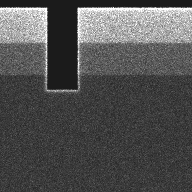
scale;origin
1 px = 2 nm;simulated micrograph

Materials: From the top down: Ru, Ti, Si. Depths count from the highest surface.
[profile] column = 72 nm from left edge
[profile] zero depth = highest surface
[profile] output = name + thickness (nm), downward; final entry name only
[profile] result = Ru 70, Ti 64, Si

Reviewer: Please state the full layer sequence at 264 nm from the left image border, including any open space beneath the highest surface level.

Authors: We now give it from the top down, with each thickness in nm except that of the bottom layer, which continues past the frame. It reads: Ru 70, Ti 64, Si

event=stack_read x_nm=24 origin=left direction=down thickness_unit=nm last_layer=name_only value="Ru 70, Ti 64, Si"